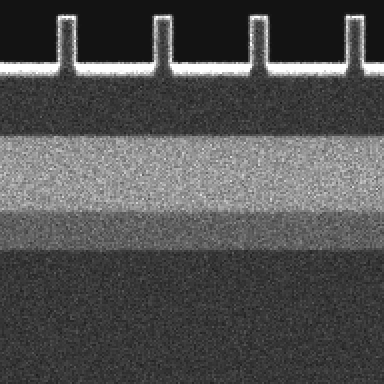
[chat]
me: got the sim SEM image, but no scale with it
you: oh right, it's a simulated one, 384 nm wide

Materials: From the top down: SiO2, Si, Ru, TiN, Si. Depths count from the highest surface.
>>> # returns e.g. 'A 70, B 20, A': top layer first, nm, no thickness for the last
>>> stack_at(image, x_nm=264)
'Si 120, Ru 76, TiN 38, Si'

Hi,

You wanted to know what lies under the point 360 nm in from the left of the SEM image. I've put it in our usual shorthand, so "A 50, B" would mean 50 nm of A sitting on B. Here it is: Si 120, Ru 76, TiN 38, Si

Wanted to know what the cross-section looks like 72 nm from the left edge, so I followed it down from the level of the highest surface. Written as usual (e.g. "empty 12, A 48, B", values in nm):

Si 120, Ru 76, TiN 38, Si